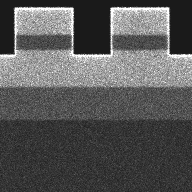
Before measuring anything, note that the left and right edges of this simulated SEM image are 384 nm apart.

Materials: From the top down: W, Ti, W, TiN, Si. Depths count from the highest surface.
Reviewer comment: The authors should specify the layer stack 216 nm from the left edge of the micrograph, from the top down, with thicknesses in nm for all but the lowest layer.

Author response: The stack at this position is empty 94, W 64, TiN 66, Si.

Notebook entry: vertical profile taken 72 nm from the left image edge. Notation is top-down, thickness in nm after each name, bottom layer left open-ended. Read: W 54, Ti 30, W 74, TiN 66, Si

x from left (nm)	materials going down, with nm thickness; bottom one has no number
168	empty 94, W 64, TiN 66, Si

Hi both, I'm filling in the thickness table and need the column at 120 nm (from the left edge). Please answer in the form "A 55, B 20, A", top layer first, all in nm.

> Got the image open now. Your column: W 54, Ti 30, W 74, TiN 66, Si